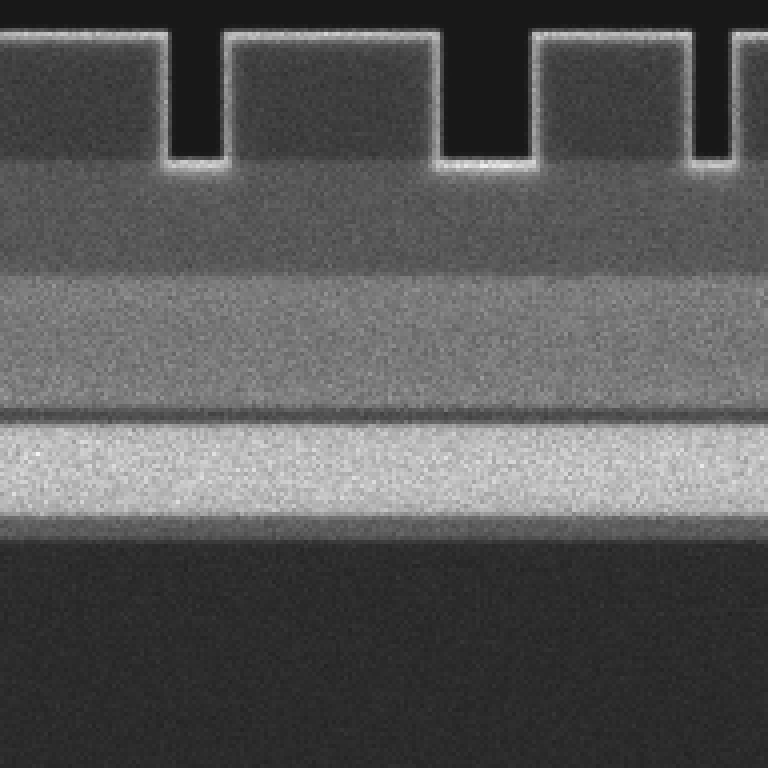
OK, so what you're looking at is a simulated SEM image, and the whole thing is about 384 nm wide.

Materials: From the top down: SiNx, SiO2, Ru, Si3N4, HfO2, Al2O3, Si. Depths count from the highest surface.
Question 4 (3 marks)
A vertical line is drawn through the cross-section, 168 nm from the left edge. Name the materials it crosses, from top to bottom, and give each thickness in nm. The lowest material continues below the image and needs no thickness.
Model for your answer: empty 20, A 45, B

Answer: SiNx 64, SiO2 58, Ru 66, Si3N4 8, HfO2 46, Al2O3 12, Si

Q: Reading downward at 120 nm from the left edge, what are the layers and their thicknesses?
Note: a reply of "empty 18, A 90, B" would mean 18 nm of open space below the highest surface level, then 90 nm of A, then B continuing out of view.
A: SiNx 64, SiO2 58, Ru 66, Si3N4 8, HfO2 46, Al2O3 12, Si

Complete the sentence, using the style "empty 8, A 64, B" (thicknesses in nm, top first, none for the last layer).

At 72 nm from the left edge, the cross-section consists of SiNx 64, SiO2 58, Ru 66, Si3N4 8, HfO2 46, Al2O3 12, Si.